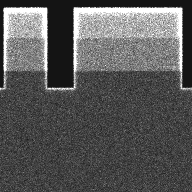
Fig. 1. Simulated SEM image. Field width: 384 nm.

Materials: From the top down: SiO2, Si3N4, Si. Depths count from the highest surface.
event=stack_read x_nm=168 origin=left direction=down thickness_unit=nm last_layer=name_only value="SiO2 60, Si3N4 66, Si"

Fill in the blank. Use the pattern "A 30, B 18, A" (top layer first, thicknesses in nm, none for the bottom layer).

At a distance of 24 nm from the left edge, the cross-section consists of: SiO2 60, Si3N4 66, Si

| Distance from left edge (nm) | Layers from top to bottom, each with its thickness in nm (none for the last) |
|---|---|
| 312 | SiO2 60, Si3N4 66, Si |